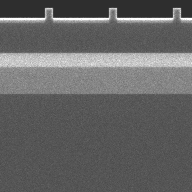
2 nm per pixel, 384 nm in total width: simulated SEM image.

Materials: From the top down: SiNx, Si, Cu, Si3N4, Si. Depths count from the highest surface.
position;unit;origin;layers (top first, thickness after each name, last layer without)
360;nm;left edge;Si 90, Cu 28, Si3N4 54, Si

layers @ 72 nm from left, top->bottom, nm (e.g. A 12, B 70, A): empty 20, SiNx 10, Si 60, Cu 28, Si3N4 54, Si